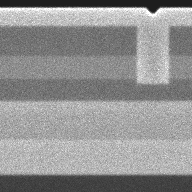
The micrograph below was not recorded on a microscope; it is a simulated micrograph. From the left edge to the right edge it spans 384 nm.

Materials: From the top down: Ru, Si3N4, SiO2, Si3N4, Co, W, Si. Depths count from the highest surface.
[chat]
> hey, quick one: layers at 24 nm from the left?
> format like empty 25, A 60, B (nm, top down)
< Ru 36, Si3N4 60, SiO2 46, Si3N4 44, Co 78, W 70, Si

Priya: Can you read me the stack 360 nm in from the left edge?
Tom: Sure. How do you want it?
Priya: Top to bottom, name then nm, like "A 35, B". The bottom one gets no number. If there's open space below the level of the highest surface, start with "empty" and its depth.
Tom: Ru 36, Si3N4 60, SiO2 46, Si3N4 44, Co 78, W 70, Si